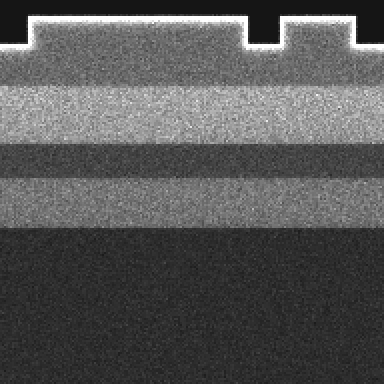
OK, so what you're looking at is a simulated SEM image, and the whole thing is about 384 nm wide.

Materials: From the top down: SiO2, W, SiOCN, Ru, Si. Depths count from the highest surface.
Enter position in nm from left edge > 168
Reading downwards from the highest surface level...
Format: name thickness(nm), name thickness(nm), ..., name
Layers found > SiO2 70, W 58, SiOCN 34, Ru 50, Si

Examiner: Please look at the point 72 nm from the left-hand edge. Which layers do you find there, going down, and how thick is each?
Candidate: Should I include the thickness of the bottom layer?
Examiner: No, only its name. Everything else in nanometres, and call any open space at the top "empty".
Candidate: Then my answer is SiO2 70, W 58, SiOCN 34, Ru 50, Si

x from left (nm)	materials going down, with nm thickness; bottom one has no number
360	empty 28, SiO2 42, W 58, SiOCN 34, Ru 50, Si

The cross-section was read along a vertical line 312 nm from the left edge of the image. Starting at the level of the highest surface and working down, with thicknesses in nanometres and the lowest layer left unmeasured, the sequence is SiO2 70, W 58, SiOCN 34, Ru 50, Si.